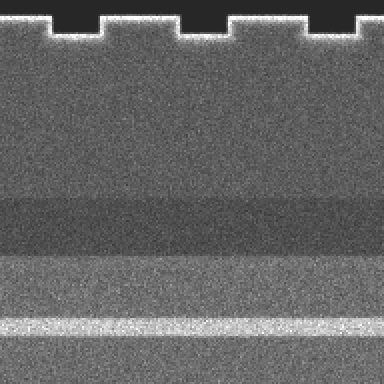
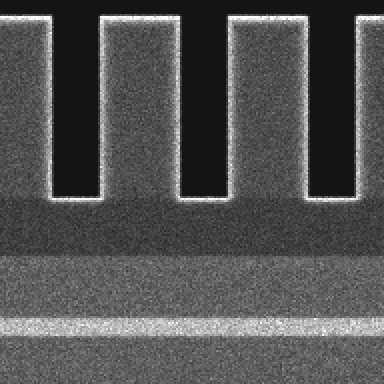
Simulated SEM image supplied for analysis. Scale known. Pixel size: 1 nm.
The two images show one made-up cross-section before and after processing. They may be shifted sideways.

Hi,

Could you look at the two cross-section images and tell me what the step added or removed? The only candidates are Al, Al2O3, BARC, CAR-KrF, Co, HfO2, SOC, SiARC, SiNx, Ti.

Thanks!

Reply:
removed SOC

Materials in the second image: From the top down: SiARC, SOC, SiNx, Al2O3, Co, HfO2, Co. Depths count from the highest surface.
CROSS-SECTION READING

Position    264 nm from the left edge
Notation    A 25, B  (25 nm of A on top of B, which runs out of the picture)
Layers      SiARC 18, SOC 164, SiNx 58, Al2O3 14, Co 48, HfO2 18, Co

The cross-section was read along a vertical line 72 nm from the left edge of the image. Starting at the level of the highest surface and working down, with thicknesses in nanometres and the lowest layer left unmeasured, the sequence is empty 182, SiNx 58, Al2O3 14, Co 48, HfO2 18, Co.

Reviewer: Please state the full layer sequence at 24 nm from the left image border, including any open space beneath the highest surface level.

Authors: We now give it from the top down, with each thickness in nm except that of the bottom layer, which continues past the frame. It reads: SiARC 18, SOC 164, SiNx 58, Al2O3 14, Co 48, HfO2 18, Co